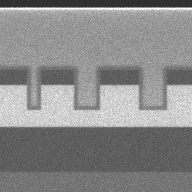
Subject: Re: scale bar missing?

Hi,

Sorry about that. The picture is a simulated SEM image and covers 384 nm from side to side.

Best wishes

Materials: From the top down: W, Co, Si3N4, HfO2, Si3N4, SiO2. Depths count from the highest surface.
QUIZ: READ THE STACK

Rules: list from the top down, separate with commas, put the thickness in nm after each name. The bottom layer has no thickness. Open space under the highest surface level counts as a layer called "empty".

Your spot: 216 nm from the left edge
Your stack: W 116, Co 8, Si3N4 30, HfO2 84, Si3N4 90, SiO2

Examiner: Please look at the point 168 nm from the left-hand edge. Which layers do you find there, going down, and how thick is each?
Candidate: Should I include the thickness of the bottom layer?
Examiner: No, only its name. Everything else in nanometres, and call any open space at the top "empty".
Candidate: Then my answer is W 196, Co 8, HfO2 34, Si3N4 90, SiO2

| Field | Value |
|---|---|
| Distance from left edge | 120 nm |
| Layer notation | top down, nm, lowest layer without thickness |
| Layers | W 116, Co 8, Si3N4 30, HfO2 84, Si3N4 90, SiO2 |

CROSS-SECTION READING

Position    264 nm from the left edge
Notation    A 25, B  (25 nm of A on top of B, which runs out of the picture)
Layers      W 116, Co 8, Si3N4 30, HfO2 84, Si3N4 90, SiO2